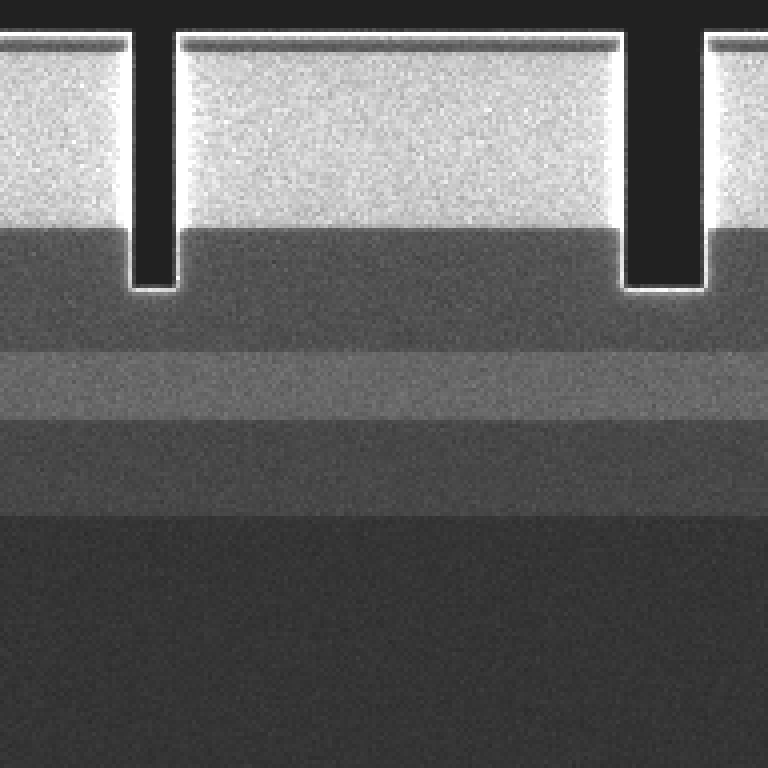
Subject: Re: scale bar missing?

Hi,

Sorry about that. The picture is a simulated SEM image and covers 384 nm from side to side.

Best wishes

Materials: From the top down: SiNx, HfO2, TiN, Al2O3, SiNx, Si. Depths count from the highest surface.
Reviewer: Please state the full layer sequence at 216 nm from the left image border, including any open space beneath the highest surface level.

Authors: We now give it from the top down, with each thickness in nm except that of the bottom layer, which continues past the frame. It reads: SiNx 10, HfO2 88, TiN 62, Al2O3 34, SiNx 48, Si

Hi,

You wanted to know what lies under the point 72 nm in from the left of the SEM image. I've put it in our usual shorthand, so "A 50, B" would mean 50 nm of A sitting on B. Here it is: empty 128, TiN 32, Al2O3 34, SiNx 48, Si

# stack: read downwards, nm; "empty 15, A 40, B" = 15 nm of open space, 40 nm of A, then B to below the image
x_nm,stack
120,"SiNx 10, HfO2 88, TiN 62, Al2O3 34, SiNx 48, Si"